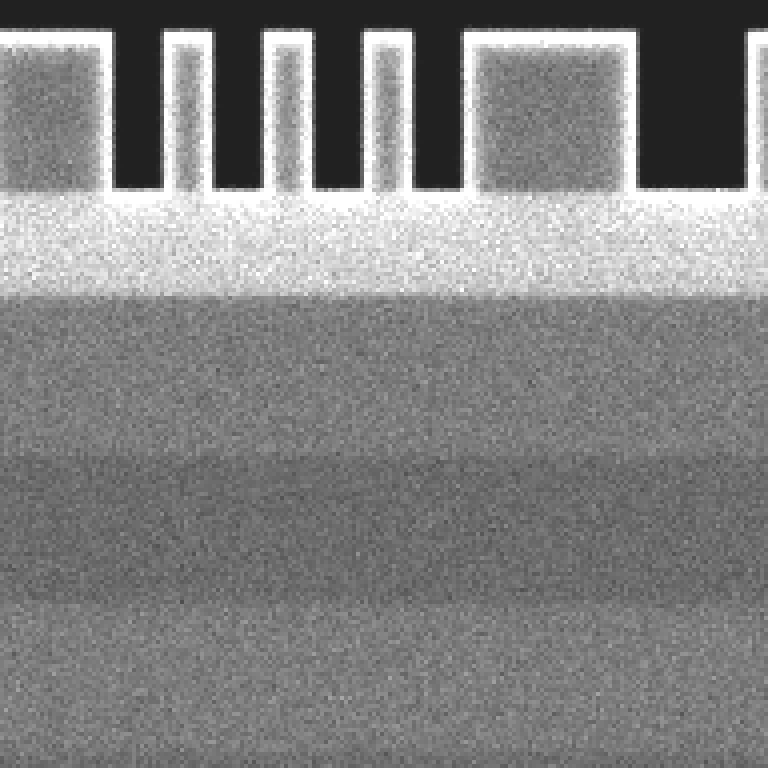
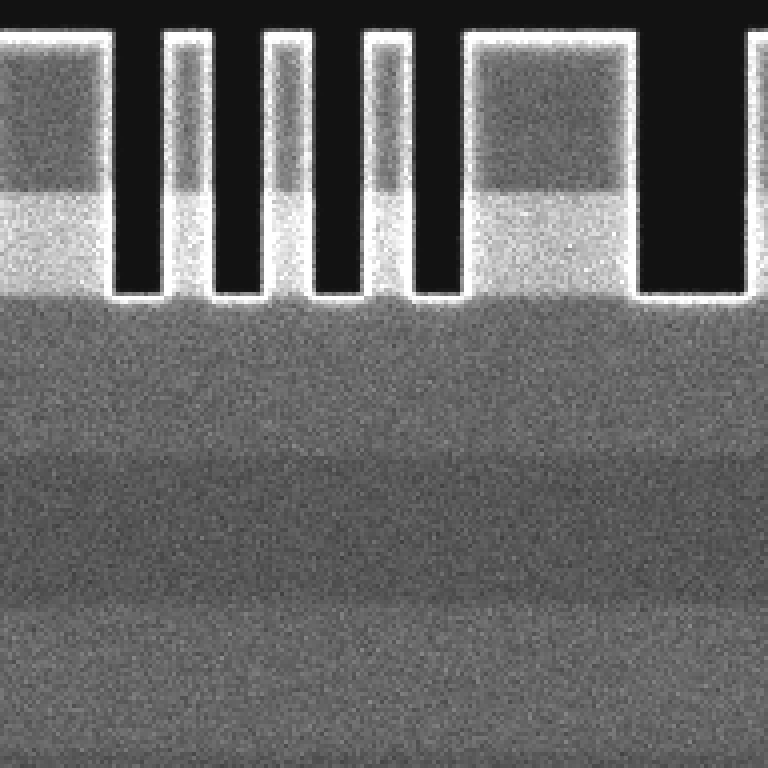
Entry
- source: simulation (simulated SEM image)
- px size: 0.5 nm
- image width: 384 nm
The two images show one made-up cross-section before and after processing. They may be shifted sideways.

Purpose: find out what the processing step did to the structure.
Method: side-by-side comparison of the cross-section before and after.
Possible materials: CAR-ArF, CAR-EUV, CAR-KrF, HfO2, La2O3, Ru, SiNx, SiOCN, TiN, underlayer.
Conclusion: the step removed Ru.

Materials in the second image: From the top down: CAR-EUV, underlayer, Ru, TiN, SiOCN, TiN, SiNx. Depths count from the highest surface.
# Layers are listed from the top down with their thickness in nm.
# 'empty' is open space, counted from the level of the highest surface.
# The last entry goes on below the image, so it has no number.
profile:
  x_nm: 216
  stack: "empty 132, TiN 80, SiOCN 74, TiN 74, SiNx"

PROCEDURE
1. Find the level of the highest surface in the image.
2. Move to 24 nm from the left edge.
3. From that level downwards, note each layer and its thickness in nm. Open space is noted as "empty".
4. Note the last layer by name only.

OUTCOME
CAR-EUV 48, underlayer 32, Ru 52, TiN 80, SiOCN 74, TiN 74, SiNx